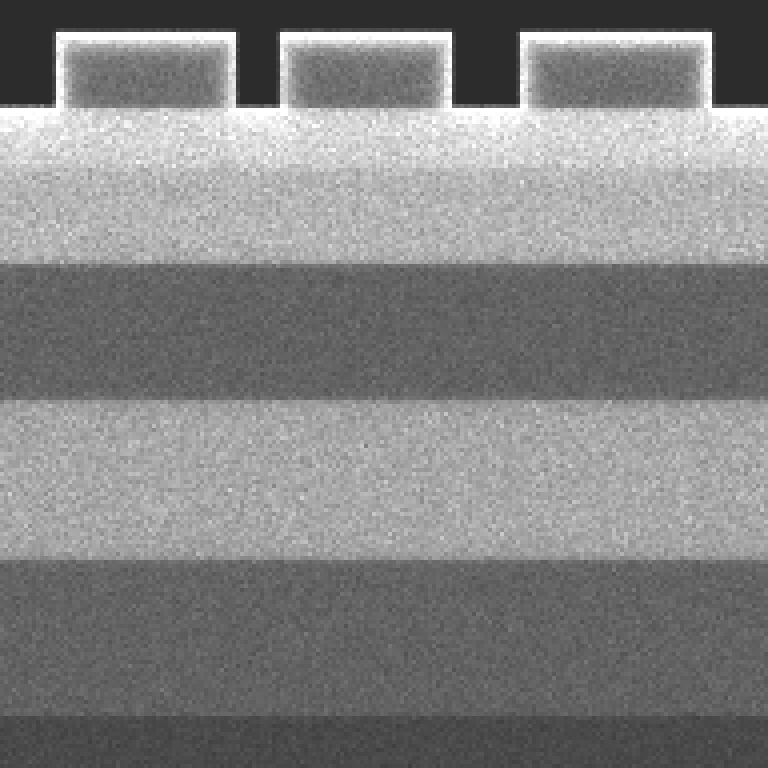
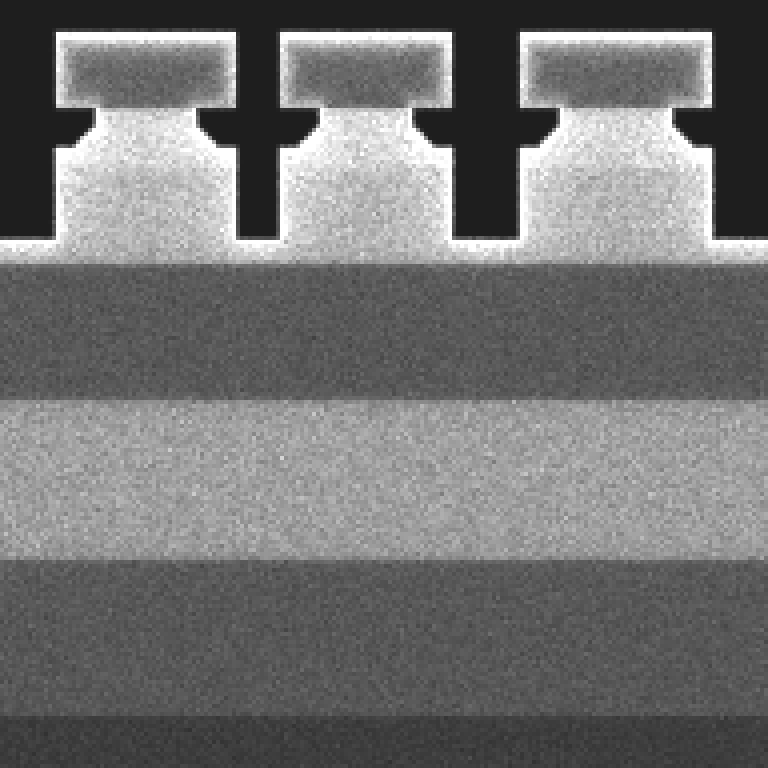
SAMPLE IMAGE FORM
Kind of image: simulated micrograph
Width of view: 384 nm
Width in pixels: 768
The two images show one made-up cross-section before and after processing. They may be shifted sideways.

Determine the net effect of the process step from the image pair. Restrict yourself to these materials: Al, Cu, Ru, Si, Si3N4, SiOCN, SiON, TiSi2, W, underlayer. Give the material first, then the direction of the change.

Ru and W: removed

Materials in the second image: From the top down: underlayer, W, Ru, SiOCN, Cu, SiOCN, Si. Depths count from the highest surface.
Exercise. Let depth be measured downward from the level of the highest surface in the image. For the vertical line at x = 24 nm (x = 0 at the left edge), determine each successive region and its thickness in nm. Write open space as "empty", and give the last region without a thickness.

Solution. empty 104, Ru 12, SiOCN 68, Cu 80, SiOCN 78, Si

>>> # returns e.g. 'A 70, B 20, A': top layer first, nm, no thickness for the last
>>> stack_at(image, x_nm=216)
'underlayer 38, empty 20, W 10, Ru 48, SiOCN 68, Cu 80, SiOCN 78, Si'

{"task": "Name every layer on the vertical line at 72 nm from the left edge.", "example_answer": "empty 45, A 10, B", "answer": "underlayer 38, W 30, Ru 48, SiOCN 68, Cu 80, SiOCN 78, Si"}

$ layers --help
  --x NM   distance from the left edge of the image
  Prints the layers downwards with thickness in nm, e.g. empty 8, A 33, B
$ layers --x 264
underlayer 38, empty 20, W 10, Ru 48, SiOCN 68, Cu 80, SiOCN 78, Si